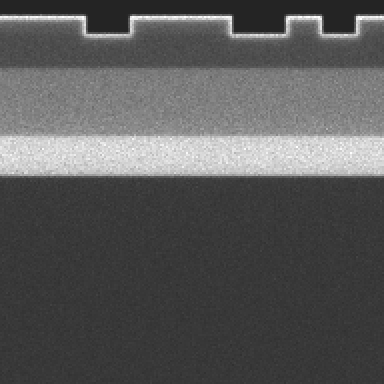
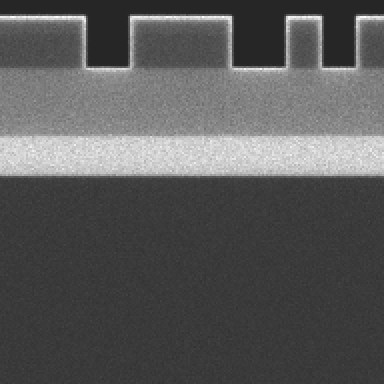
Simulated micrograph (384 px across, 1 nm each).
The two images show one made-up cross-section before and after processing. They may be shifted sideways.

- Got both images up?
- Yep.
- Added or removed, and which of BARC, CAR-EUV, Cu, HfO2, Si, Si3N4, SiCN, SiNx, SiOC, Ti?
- removed, SiNx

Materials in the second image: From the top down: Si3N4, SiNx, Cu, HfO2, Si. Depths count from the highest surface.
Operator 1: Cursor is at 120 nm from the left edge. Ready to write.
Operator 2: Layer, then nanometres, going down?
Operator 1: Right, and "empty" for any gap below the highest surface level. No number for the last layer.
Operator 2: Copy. empty 52, Cu 68, HfO2 40, Si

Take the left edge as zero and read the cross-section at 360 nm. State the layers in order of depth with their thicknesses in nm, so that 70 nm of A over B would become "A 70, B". Si3N4 18, SiNx 34, Cu 68, HfO2 40, Si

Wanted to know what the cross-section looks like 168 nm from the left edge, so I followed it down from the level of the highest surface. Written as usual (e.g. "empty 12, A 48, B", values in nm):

Si3N4 18, SiNx 34, Cu 68, HfO2 40, Si